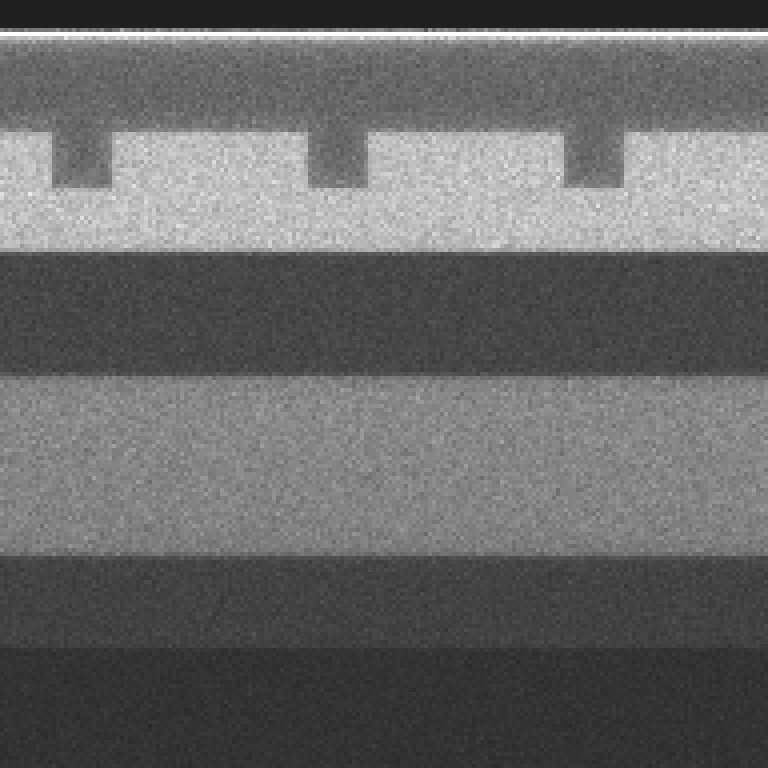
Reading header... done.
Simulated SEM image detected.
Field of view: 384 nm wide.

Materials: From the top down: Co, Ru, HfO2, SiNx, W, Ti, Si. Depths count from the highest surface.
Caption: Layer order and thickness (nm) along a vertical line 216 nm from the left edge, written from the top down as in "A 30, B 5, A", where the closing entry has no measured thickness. Co 42, Ru 8, HfO2 60, SiNx 62, W 90, Ti 46, Si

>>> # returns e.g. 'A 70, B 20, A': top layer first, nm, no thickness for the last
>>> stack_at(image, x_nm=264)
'Co 42, Ru 8, HfO2 60, SiNx 62, W 90, Ti 46, Si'